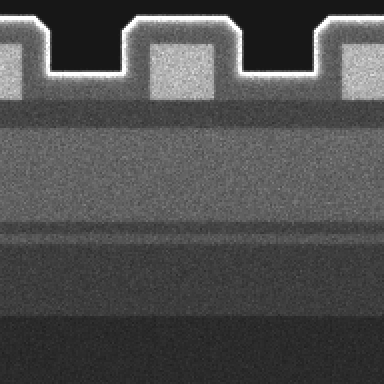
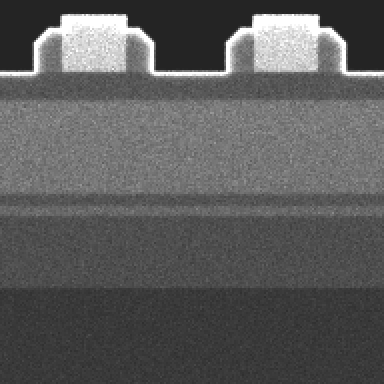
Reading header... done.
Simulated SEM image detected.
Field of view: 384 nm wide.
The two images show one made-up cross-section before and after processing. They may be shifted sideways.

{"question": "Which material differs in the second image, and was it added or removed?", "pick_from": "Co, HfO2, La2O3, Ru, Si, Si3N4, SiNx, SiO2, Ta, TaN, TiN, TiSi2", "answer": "SiO2, removed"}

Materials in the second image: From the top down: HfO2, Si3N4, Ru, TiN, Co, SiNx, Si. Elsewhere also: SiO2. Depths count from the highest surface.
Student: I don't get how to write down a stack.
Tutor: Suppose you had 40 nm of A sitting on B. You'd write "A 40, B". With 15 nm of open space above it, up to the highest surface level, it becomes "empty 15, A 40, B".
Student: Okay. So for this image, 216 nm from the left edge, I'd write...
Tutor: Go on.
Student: empty 56, Si3N4 28, Ru 94, TiN 12, Co 10, SiNx 72, Si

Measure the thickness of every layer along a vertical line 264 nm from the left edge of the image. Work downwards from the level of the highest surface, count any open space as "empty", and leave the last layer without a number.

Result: HfO2 56, Si3N4 28, Ru 94, TiN 12, Co 10, SiNx 72, Si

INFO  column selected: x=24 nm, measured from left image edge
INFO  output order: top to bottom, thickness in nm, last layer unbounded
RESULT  empty 56, Si3N4 28, Ru 94, TiN 12, Co 10, SiNx 72, Si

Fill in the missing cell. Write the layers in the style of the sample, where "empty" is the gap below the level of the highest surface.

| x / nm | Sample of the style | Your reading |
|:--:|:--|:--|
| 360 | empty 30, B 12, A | empty 56, Si3N4 28, Ru 94, TiN 12, Co 10, SiNx 72, Si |